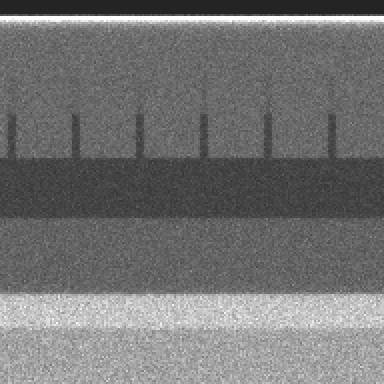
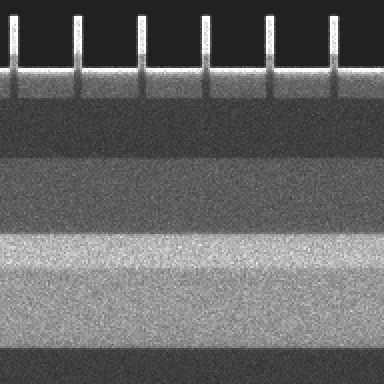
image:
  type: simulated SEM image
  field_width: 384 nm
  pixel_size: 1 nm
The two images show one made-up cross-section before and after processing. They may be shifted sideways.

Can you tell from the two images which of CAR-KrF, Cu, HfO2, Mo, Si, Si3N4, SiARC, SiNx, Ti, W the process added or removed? Yes, it removed SiARC.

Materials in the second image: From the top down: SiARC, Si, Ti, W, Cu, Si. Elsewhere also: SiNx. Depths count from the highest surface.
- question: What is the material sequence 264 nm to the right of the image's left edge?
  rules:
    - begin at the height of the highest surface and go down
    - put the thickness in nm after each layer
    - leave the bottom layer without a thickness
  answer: empty 52, SiARC 30, Si 60, Ti 76, W 34, Cu 80, Si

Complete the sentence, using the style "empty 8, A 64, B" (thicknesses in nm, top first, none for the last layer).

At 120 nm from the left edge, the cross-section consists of empty 52, SiARC 30, Si 60, Ti 76, W 34, Cu 80, Si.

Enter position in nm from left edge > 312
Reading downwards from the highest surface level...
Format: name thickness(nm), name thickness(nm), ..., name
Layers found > empty 52, SiARC 30, Si 60, Ti 76, W 34, Cu 80, Si